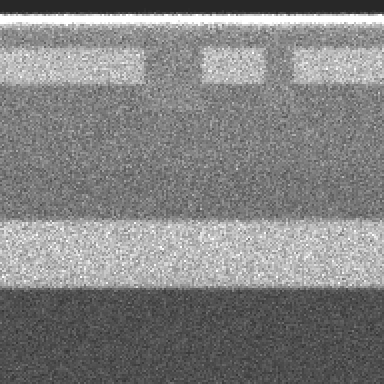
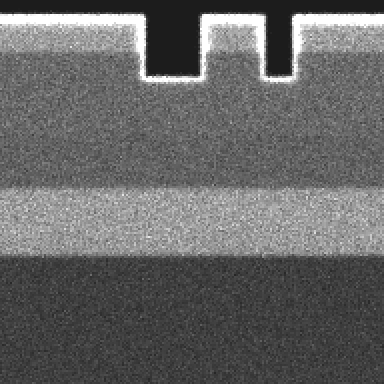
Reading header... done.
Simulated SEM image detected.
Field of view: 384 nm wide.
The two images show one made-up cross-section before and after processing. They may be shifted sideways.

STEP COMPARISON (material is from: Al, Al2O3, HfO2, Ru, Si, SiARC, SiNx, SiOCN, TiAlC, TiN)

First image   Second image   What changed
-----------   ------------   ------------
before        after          SiARC, removed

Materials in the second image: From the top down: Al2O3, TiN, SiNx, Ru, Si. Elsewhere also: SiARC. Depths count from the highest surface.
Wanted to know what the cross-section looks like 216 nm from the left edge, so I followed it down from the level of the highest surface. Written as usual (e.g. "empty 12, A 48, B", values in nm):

Al2O3 36, TiN 84, SiNx 52, Ru 68, Si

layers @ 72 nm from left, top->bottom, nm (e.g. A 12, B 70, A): Al2O3 36, TiN 84, SiNx 52, Ru 68, Si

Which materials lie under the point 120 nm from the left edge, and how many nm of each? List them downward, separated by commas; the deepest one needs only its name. Al2O3 36, TiN 84, SiNx 52, Ru 68, Si